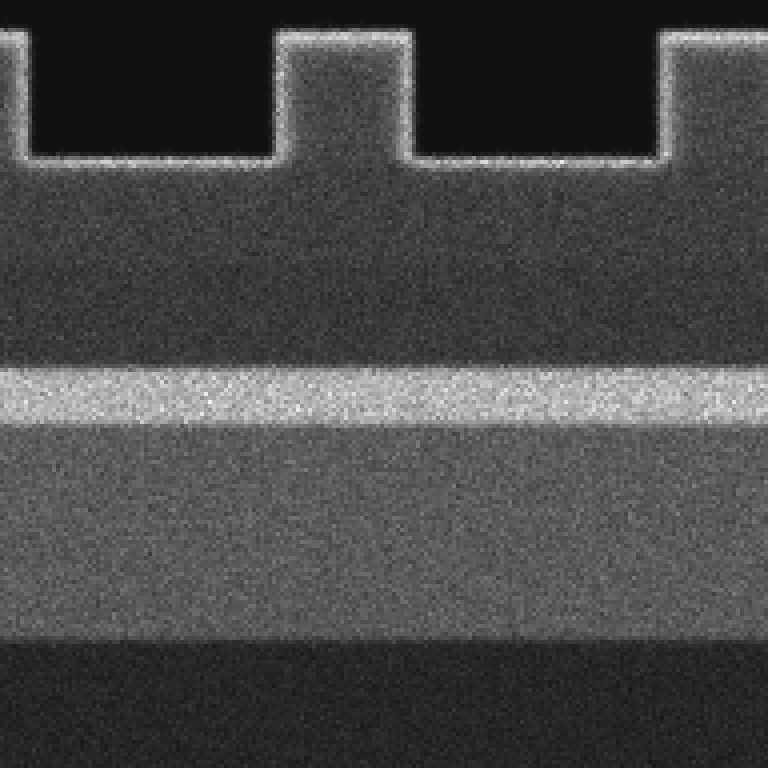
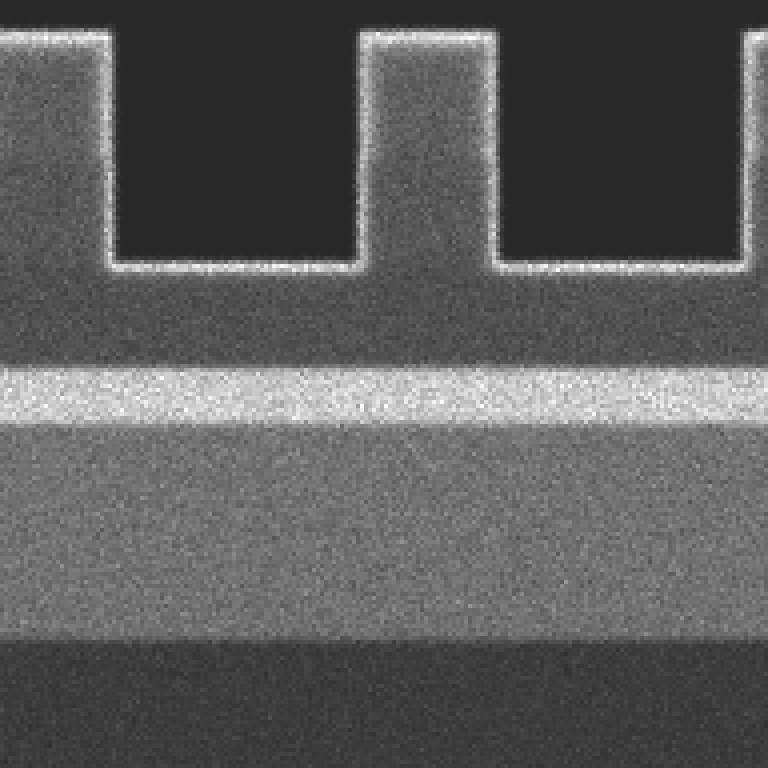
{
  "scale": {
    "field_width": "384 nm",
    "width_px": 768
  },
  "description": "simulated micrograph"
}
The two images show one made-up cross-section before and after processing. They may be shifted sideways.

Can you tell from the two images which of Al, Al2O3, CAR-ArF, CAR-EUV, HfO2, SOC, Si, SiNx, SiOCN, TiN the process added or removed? Yes, it removed TiN.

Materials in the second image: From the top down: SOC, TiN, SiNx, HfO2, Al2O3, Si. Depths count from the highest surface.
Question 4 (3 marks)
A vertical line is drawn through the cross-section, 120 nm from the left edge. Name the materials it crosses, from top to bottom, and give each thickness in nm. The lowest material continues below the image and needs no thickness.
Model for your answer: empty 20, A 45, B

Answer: empty 116, SiNx 52, HfO2 28, Al2O3 108, Si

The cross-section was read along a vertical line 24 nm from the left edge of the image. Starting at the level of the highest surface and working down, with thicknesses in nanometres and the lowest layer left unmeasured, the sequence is SOC 64, TiN 52, SiNx 52, HfO2 28, Al2O3 108, Si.